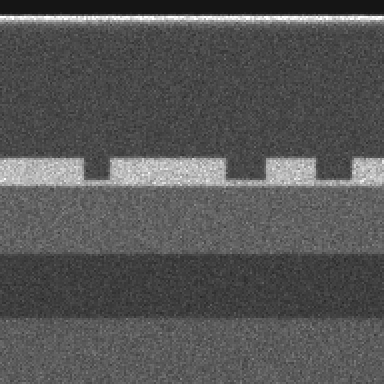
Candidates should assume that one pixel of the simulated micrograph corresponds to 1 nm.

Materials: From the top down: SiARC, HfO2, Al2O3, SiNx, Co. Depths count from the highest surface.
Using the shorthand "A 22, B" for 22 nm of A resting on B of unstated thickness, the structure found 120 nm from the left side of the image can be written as SiARC 142, HfO2 28, Al2O3 68, SiNx 64, Co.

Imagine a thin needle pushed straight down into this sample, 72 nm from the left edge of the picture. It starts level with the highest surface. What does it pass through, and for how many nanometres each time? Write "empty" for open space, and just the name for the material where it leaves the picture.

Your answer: SiARC 142, HfO2 28, Al2O3 68, SiNx 64, Co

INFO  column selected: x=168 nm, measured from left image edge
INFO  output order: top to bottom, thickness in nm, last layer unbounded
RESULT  SiARC 142, HfO2 28, Al2O3 68, SiNx 64, Co